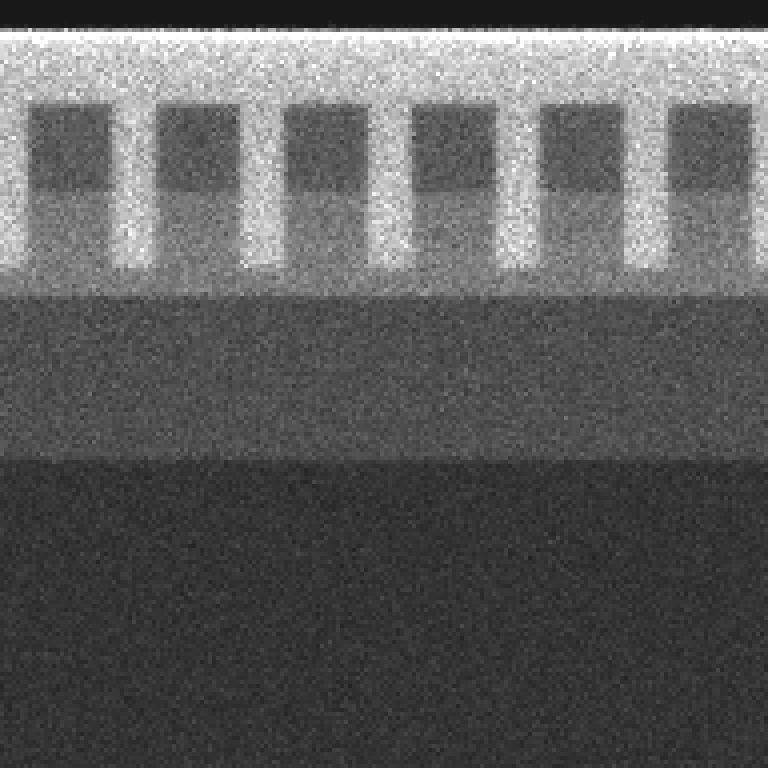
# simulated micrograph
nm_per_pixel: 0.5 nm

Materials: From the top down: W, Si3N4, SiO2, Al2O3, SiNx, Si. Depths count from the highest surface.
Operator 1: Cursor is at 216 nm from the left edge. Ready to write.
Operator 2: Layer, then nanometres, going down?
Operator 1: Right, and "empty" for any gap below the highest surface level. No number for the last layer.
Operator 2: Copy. W 36, Si3N4 44, SiO2 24, Al2O3 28, SiNx 82, Si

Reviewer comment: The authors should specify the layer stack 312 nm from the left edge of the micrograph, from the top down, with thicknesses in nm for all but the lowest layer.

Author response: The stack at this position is W 118, Al2O3 14, SiNx 82, Si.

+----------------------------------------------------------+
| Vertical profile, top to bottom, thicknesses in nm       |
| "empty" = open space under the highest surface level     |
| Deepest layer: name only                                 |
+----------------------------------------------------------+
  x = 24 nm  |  W 36, Si3N4 44, SiO2 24, Al2O3 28, SiNx 82, Si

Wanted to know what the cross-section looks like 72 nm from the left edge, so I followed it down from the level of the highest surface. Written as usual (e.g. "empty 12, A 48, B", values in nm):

W 118, Al2O3 14, SiNx 82, Si